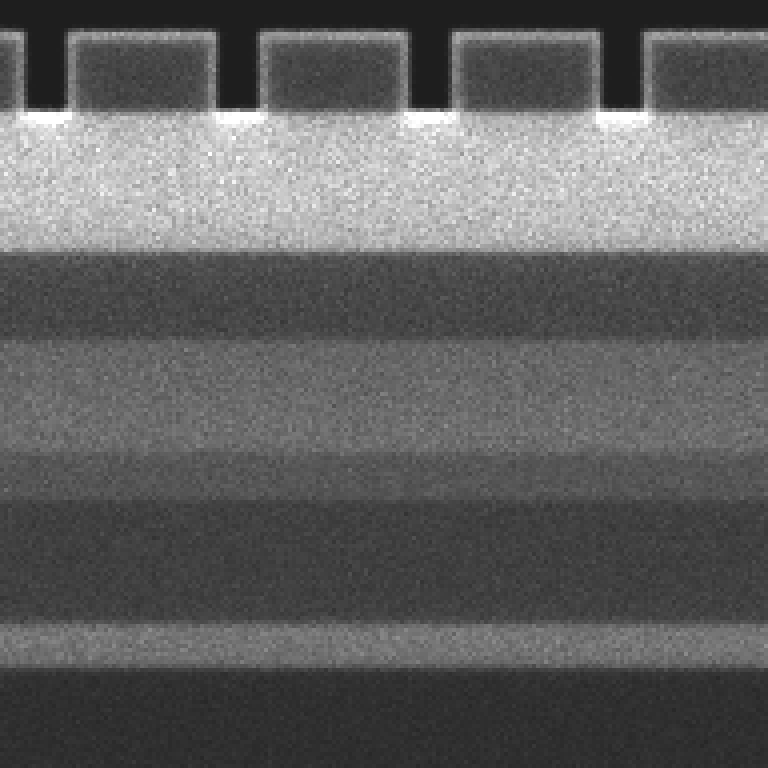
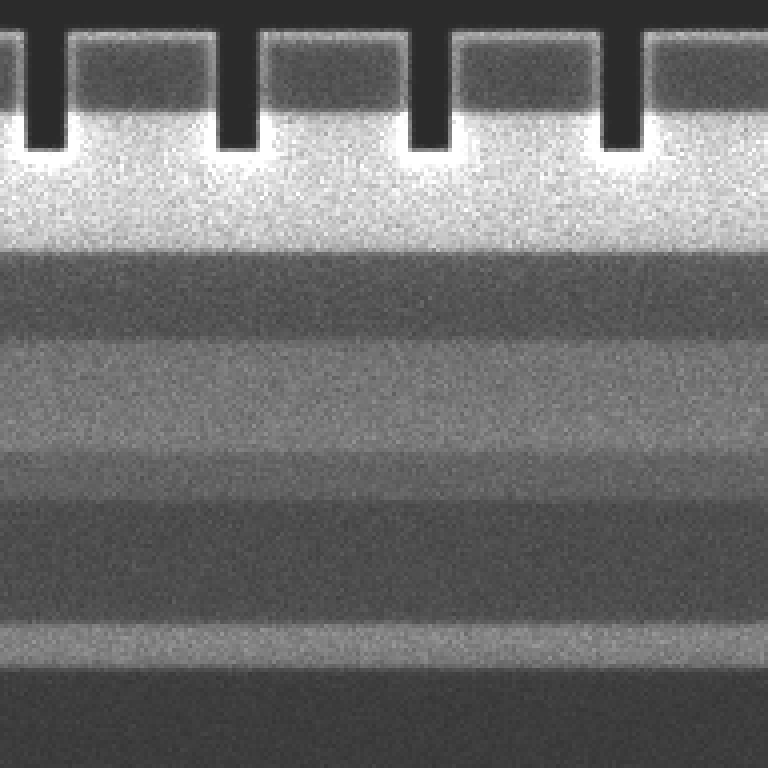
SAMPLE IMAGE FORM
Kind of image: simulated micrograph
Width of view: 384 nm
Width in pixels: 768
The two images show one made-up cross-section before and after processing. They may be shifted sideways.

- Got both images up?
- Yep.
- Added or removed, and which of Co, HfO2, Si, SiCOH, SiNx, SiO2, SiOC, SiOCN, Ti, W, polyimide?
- removed, HfO2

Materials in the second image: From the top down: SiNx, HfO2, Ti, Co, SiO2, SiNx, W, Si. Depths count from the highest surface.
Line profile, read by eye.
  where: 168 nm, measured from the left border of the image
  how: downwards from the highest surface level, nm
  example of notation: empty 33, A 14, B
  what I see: SiNx 40, HfO2 70, Ti 44, Co 56, SiO2 24, SiNx 62, W 22, Si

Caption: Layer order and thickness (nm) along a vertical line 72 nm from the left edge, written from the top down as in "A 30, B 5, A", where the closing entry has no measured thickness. SiNx 40, HfO2 70, Ti 44, Co 56, SiO2 24, SiNx 62, W 22, Si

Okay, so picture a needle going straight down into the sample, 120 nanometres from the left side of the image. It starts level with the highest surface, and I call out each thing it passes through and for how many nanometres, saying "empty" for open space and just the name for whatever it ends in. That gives empty 60, HfO2 50, Ti 44, Co 56, SiO2 24, SiNx 62, W 22, Si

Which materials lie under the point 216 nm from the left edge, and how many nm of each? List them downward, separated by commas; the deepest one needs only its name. empty 60, HfO2 50, Ti 44, Co 56, SiO2 24, SiNx 62, W 22, Si